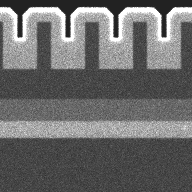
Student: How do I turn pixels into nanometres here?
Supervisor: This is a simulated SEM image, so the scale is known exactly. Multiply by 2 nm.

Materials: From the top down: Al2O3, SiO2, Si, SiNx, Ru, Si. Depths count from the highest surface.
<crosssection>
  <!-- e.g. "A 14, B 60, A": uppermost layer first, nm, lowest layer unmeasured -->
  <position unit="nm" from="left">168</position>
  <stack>Al2O3 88, SiO2 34, Si 60, SiNx 44, Ru 34, Si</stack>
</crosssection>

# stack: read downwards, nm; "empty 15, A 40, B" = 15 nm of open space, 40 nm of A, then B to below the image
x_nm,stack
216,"empty 6, Al2O3 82, SiO2 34, Si 60, SiNx 44, Ru 34, Si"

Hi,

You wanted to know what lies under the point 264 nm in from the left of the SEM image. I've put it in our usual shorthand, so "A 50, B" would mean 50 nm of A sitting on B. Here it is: Al2O3 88, SiO2 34, Si 60, SiNx 44, Ru 34, Si